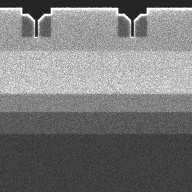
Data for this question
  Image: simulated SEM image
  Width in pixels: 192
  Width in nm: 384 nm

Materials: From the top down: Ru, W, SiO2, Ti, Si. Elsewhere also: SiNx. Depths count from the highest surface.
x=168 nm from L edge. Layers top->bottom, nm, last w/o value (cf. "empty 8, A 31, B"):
Ru 86, W 86, SiO2 36, Ti 44, Si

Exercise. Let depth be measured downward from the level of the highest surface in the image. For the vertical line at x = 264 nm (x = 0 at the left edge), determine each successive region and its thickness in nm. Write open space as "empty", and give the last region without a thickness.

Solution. empty 58, Ru 28, W 86, SiO2 36, Ti 44, Si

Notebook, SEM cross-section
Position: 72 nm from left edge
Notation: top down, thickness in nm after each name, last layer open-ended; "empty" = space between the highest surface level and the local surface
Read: empty 58, Ru 28, W 86, SiO2 36, Ti 44, Si